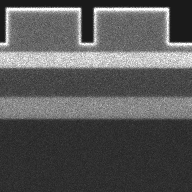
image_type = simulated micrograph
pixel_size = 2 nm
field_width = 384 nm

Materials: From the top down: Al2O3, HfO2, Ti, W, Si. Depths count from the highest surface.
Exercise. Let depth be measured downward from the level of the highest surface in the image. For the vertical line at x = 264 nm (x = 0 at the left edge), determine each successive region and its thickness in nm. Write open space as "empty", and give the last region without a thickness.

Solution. Al2O3 88, HfO2 32, Ti 58, W 44, Si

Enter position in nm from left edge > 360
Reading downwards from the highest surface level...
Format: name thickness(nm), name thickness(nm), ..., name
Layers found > empty 70, Al2O3 18, HfO2 32, Ti 58, W 44, Si